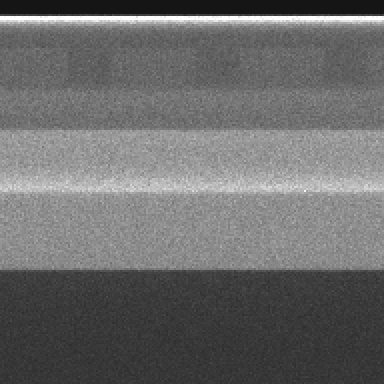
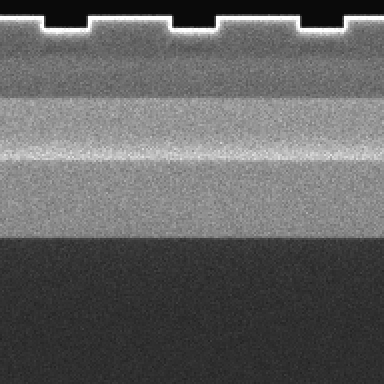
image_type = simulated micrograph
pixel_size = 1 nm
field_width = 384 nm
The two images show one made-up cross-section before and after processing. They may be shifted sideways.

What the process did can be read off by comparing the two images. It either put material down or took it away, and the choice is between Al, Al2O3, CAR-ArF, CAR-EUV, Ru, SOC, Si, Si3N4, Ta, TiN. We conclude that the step removed SOC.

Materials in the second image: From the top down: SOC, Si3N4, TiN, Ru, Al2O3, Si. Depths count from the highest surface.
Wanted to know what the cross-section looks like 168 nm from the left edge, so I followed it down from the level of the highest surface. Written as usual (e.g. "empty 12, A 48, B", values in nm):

Si3N4 42, TiN 40, Ru 62, Al2O3 78, Si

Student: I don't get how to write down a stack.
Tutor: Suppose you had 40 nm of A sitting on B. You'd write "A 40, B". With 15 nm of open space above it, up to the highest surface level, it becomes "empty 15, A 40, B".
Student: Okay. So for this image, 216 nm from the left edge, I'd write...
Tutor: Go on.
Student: Si3N4 42, TiN 40, Ru 62, Al2O3 78, Si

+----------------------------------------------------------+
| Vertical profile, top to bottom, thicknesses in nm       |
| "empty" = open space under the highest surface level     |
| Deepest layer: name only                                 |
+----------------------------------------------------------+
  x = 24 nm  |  Si3N4 42, TiN 40, Ru 62, Al2O3 78, Si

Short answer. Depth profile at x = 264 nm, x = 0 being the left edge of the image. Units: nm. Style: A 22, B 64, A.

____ Si3N4 42, TiN 40, Ru 62, Al2O3 78, Si